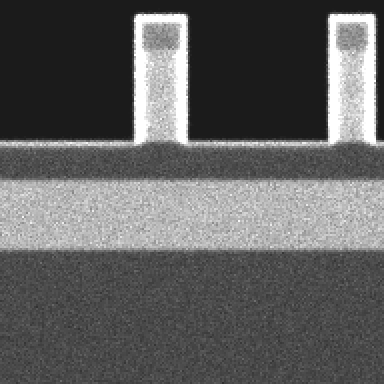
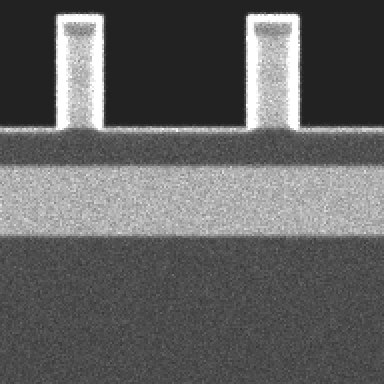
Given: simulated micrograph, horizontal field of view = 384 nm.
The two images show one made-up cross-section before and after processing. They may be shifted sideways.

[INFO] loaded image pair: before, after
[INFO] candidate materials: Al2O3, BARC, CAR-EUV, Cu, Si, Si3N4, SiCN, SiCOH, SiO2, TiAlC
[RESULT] removed Si3N4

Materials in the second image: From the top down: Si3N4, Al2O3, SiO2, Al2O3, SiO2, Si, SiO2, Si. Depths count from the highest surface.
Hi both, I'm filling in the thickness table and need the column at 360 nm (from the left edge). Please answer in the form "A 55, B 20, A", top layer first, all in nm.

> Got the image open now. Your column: empty 112, Si 38, SiO2 70, Si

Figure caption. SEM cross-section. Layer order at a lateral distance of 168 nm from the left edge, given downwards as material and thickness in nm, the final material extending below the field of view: empty 112, Si 38, SiO2 70, Si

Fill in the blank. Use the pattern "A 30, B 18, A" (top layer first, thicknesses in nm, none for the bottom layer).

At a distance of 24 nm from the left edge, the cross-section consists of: empty 112, Si 38, SiO2 70, Si